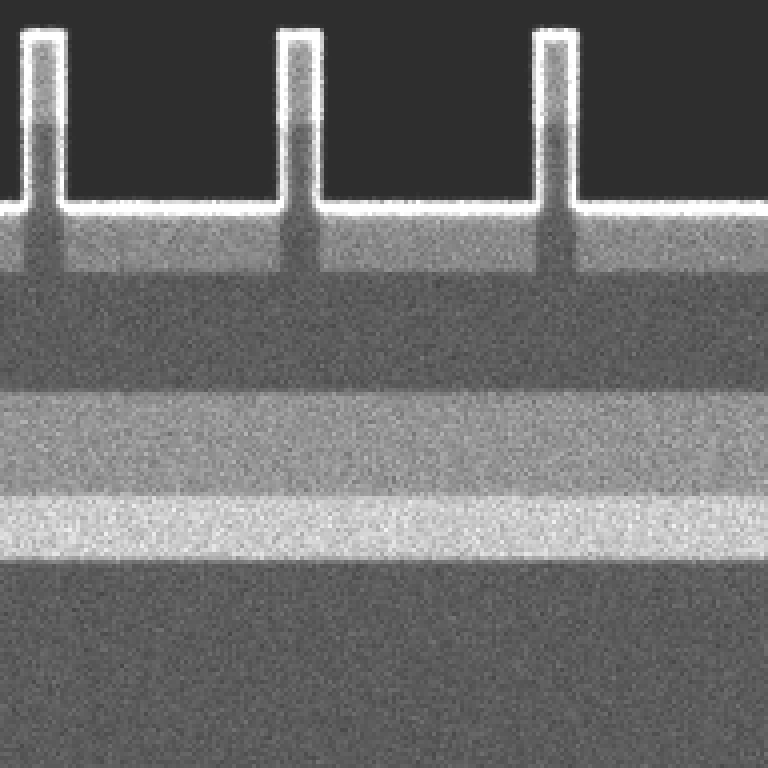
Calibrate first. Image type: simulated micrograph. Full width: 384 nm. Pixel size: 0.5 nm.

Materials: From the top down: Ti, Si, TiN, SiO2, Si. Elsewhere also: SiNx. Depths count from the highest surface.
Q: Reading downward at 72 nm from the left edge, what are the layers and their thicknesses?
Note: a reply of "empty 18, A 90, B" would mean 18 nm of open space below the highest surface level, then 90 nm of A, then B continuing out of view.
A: empty 86, SiNx 34, Si 60, TiN 52, SiO2 32, Si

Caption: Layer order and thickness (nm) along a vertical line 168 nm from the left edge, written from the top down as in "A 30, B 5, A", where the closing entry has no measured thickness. empty 86, SiNx 34, Si 60, TiN 52, SiO2 32, Si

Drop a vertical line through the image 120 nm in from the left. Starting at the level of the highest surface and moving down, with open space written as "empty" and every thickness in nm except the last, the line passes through empty 86, SiNx 34, Si 60, TiN 52, SiO2 32, Si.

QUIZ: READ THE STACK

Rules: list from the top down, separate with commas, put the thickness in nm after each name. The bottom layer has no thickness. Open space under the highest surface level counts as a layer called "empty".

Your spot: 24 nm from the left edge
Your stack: Ti 46, Si 134, TiN 52, SiO2 32, Si